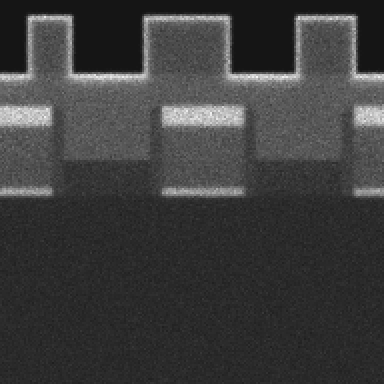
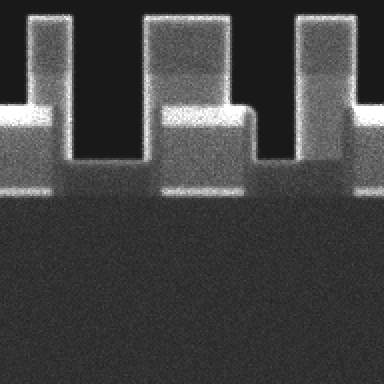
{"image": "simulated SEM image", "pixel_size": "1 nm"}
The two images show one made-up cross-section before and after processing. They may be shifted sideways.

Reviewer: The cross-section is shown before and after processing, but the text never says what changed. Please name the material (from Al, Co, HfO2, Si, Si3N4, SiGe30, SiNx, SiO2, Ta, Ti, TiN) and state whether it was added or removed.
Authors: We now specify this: SiO2, removed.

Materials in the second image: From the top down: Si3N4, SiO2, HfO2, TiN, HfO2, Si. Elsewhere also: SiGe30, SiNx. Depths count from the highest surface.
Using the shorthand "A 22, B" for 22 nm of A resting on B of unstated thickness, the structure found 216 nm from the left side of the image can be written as Si3N4 58, SiO2 32, HfO2 20, TiN 62, HfO2 8, Si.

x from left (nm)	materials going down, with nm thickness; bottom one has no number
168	Si3N4 58, SiO2 32, HfO2 20, TiN 62, HfO2 8, Si